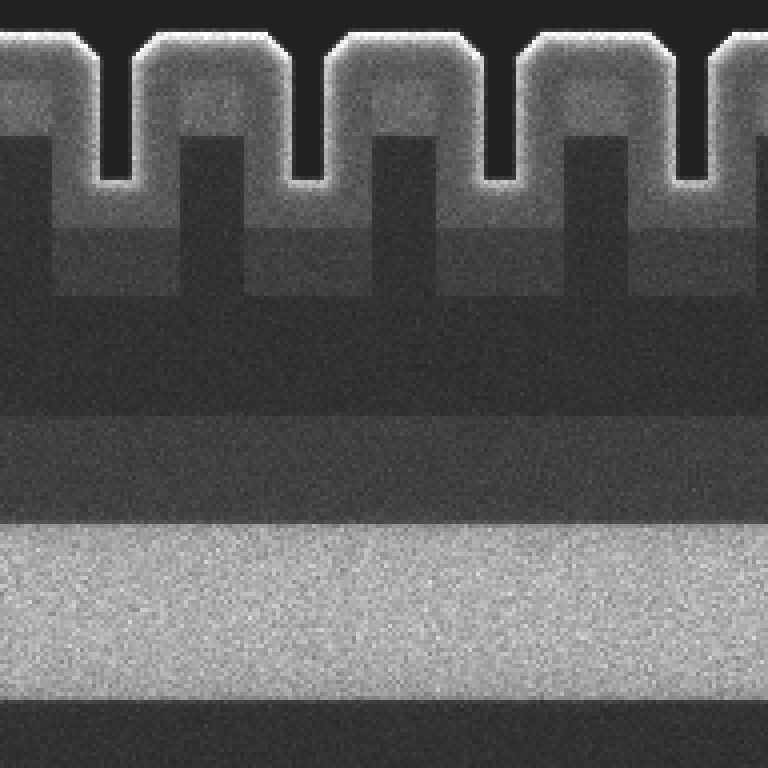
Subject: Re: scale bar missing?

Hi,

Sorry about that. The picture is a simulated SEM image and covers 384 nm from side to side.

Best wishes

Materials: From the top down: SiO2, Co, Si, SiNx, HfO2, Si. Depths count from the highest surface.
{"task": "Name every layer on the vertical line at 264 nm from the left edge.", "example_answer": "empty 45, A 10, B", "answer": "empty 6, SiO2 92, SiNx 34, Si 60, SiNx 54, HfO2 88, Si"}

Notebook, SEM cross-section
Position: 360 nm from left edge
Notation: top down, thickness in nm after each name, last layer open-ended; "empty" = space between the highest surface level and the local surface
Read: empty 6, SiO2 92, SiNx 34, Si 60, SiNx 54, HfO2 88, Si